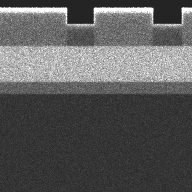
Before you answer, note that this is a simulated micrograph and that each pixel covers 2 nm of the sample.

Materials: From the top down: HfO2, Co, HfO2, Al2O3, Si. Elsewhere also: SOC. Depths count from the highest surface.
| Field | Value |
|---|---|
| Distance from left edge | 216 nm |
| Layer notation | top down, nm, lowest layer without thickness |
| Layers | HfO2 10, Co 66, HfO2 72, Al2O3 24, Si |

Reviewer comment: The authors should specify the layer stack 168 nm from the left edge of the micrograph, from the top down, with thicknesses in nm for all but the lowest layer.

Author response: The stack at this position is empty 32, SOC 44, HfO2 72, Al2O3 24, Si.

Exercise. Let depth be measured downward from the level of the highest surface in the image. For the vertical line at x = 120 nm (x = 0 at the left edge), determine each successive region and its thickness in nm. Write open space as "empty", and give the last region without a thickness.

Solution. HfO2 10, Co 66, HfO2 72, Al2O3 24, Si